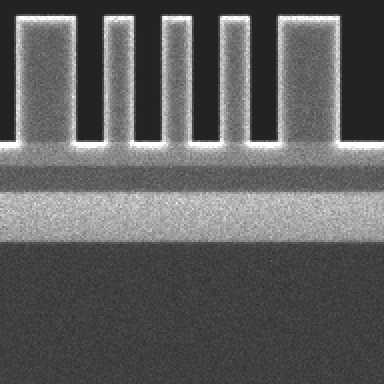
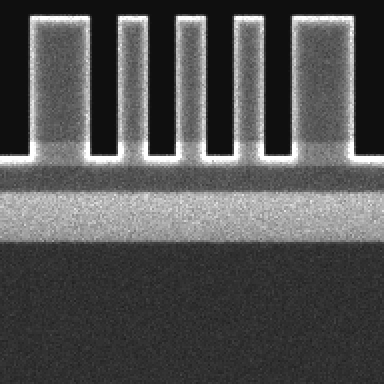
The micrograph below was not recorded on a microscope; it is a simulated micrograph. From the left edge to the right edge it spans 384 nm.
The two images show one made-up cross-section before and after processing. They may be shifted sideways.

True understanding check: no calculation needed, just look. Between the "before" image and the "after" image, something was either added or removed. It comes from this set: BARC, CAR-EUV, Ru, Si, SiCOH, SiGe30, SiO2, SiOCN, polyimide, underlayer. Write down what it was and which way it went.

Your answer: SiO2 (removed)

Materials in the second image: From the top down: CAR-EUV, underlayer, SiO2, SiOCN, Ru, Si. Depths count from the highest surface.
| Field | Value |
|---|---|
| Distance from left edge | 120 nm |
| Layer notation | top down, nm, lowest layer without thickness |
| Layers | CAR-EUV 74, underlayer 52, SiO2 24, SiOCN 26, Ru 50, Si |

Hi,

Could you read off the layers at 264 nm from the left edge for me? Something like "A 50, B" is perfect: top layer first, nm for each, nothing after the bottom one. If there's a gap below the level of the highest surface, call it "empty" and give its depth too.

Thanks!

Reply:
empty 140, SiO2 10, SiOCN 26, Ru 50, Si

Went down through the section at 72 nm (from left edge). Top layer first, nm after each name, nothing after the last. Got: CAR-EUV 74, underlayer 52, SiO2 24, SiOCN 26, Ru 50, Si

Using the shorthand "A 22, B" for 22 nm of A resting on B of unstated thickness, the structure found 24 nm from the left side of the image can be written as empty 140, SiO2 10, SiOCN 26, Ru 50, Si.